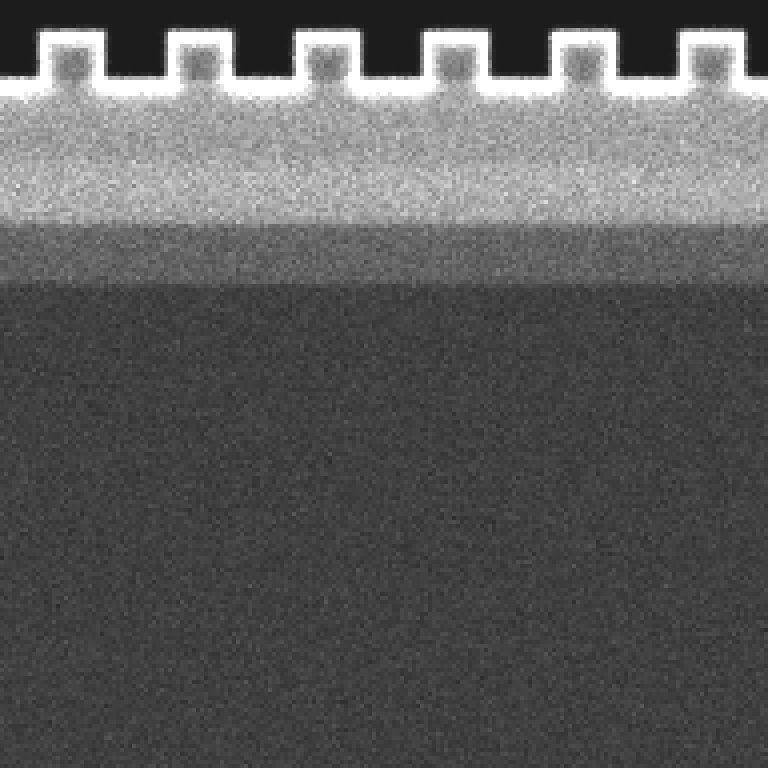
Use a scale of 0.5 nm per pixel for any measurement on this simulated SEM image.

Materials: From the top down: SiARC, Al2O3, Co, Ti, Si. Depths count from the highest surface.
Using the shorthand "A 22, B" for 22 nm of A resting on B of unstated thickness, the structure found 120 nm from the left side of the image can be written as empty 24, Al2O3 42, Co 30, Ti 30, Si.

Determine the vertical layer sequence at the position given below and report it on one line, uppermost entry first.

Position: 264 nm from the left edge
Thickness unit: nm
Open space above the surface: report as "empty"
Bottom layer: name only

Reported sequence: empty 24, Al2O3 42, Co 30, Ti 30, Si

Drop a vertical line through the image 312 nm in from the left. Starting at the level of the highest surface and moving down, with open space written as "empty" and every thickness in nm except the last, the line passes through empty 24, Al2O3 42, Co 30, Ti 30, Si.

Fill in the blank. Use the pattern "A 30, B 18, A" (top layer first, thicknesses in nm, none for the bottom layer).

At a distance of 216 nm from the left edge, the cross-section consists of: SiARC 24, Al2O3 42, Co 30, Ti 30, Si